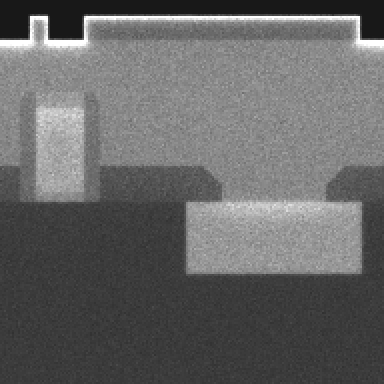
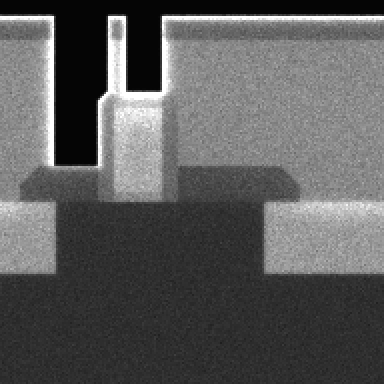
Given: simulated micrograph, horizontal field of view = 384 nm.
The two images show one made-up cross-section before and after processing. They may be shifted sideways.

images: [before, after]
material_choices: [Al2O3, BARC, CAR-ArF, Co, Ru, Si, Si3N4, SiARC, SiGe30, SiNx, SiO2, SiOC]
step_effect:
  removed: SiO2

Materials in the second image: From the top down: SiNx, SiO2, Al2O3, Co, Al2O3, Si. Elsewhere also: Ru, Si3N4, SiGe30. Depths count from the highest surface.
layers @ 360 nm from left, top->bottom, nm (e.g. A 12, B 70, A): SiNx 24, SiO2 162, Ru 72, Si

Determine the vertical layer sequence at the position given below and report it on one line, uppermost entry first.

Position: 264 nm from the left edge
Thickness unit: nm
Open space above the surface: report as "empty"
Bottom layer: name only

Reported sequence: SiNx 24, SiO2 126, SiGe30 36, Ru 72, Si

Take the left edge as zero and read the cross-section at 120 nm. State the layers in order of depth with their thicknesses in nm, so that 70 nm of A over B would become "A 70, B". SiNx 24, SiO2 52, Al2O3 16, Co 84, Al2O3 10, Si